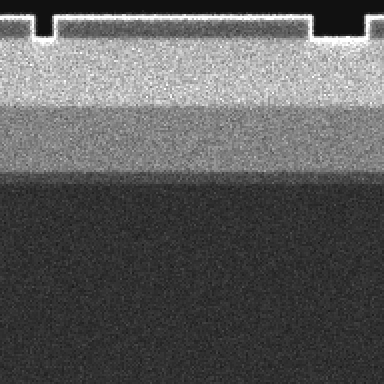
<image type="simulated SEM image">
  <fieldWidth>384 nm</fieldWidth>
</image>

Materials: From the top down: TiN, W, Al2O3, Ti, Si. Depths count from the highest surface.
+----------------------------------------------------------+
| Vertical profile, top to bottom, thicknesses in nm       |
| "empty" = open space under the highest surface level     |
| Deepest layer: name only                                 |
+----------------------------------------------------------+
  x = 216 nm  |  TiN 22, W 68, Al2O3 66, Ti 12, Si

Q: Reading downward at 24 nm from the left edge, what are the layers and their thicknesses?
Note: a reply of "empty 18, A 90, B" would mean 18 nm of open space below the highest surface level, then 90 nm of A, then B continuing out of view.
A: TiN 22, W 68, Al2O3 66, Ti 12, Si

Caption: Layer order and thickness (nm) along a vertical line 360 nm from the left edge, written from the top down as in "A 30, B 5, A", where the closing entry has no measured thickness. empty 22, W 68, Al2O3 66, Ti 12, Si